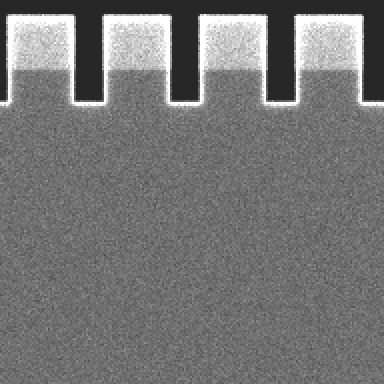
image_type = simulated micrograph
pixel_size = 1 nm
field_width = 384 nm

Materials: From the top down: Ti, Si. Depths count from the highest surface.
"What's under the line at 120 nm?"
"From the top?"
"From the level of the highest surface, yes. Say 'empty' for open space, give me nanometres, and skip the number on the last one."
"Ti 54, Si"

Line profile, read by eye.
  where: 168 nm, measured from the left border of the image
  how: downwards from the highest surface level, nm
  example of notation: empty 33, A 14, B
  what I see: Ti 54, Si